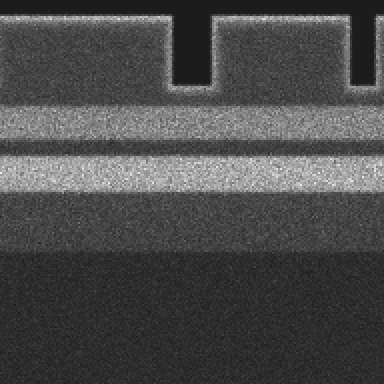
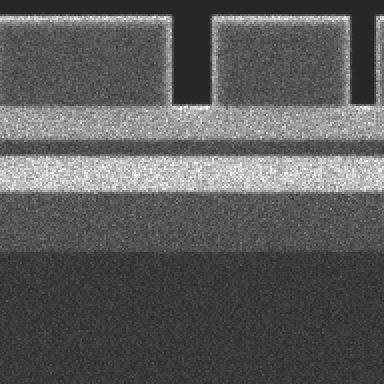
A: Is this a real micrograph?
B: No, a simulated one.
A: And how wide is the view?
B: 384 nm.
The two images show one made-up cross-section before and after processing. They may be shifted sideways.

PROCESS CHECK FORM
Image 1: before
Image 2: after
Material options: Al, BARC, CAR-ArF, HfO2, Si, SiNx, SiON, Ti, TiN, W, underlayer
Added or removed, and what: removed, underlayer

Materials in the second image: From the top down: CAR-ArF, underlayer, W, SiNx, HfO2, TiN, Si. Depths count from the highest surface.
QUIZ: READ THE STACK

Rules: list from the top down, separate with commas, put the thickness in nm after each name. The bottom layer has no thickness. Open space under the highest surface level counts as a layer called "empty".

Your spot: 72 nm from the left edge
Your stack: CAR-ArF 70, underlayer 20, W 34, SiNx 16, HfO2 36, TiN 60, Si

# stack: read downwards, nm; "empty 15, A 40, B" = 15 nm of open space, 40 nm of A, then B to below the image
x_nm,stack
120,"CAR-ArF 70, underlayer 20, W 34, SiNx 16, HfO2 36, TiN 60, Si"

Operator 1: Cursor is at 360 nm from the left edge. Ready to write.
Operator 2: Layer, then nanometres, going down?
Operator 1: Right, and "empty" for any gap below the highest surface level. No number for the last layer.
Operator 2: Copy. empty 90, W 34, SiNx 16, HfO2 36, TiN 60, Si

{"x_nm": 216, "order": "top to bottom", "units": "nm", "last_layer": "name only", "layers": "CAR-ArF 70, underlayer 20, W 34, SiNx 16, HfO2 36, TiN 60, Si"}